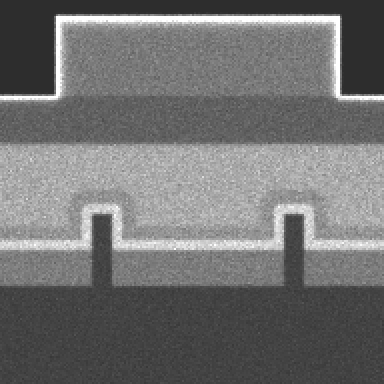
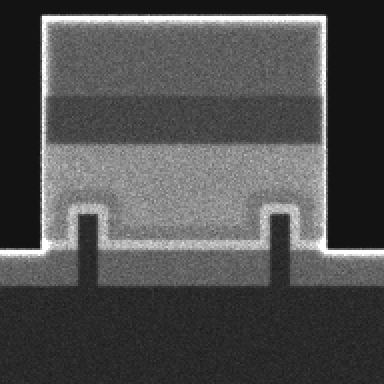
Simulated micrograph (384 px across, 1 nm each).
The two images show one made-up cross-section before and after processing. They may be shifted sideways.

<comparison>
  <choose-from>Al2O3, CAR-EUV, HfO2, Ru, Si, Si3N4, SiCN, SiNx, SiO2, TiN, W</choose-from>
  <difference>HfO2 and Ru and Si3N4 and W removed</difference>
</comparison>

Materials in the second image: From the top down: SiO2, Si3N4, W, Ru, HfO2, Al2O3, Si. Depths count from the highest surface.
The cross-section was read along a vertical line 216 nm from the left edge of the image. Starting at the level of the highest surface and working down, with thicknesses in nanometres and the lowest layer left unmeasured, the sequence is SiO2 80, Si3N4 48, W 82, Ru 14, HfO2 10, Al2O3 36, Si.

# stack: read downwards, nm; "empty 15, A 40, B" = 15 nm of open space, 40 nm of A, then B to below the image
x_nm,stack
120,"SiO2 80, Si3N4 48, W 56, Ru 40, HfO2 10, Al2O3 36, Si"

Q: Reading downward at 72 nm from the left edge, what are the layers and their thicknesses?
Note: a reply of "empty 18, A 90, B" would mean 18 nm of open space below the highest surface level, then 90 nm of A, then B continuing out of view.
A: SiO2 80, Si3N4 48, W 46, Ru 14, HfO2 46, Al2O3 36, Si